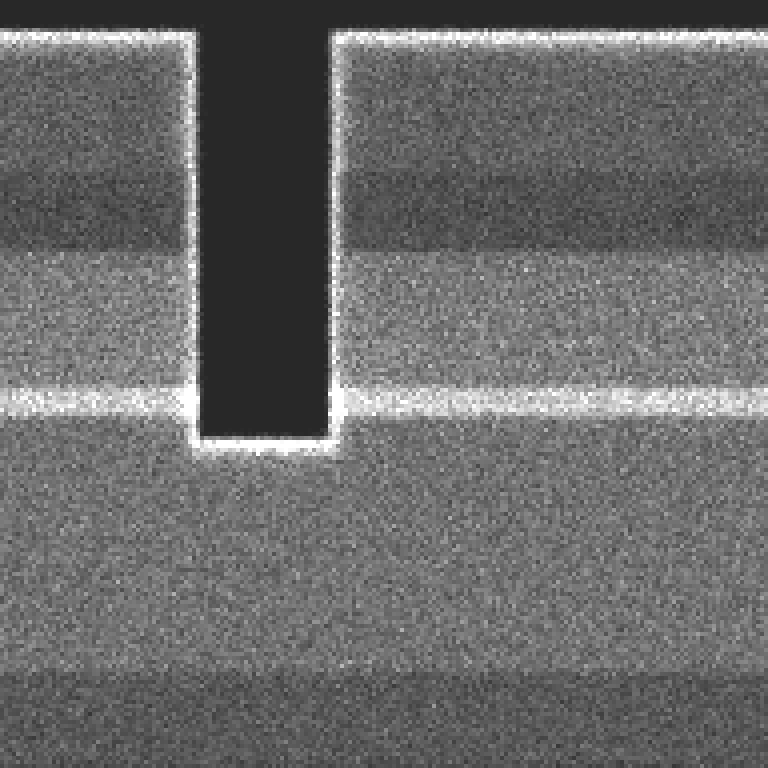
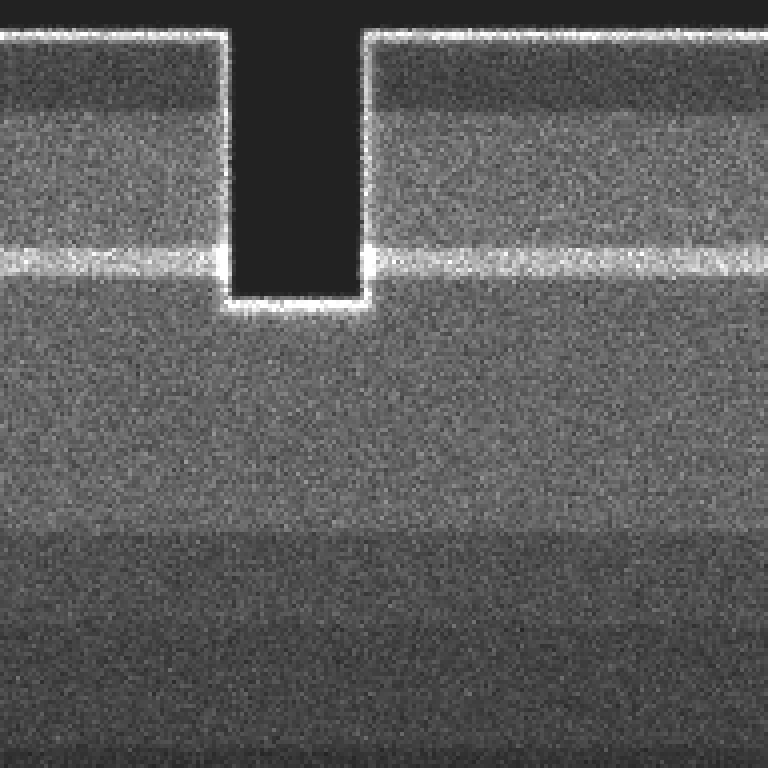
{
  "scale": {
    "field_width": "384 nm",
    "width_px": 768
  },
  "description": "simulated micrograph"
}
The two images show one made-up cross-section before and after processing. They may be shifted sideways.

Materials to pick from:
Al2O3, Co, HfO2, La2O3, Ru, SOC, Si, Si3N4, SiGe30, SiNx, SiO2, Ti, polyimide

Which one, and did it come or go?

SOC - removed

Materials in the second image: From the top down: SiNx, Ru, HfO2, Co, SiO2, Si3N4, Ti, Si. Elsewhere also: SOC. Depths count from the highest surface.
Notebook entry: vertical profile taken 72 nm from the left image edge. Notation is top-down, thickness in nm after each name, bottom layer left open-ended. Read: SiNx 40, Ru 68, HfO2 14, Co 12, SiO2 116, Si3N4 46, Ti 62, Si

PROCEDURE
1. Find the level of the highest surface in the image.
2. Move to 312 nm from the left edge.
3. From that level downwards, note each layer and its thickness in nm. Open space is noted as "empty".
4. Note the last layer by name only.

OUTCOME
SiNx 40, Ru 68, HfO2 14, Co 12, SiO2 116, Si3N4 46, Ti 62, Si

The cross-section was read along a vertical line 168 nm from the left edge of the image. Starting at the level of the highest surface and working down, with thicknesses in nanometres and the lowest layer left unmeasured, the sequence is empty 134, SiO2 116, Si3N4 46, Ti 62, Si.